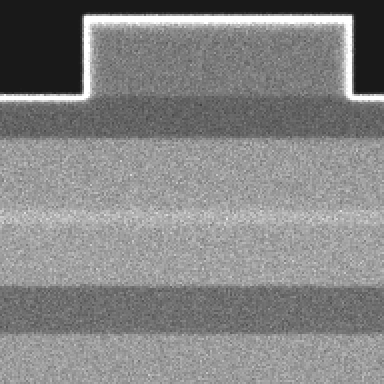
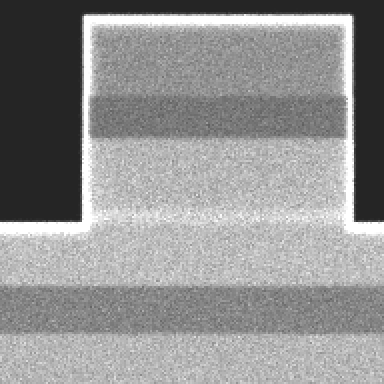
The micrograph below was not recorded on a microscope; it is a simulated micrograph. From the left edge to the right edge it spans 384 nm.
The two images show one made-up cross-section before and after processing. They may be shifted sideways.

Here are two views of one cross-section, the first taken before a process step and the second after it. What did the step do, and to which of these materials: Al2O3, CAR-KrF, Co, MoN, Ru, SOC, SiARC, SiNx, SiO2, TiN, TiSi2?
It removed Co and Ru and SiNx.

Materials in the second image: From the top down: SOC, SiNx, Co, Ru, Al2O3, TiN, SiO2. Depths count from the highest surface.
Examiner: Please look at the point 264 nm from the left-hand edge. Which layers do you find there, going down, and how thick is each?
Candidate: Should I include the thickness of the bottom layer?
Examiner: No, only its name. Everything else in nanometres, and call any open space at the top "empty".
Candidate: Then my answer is SOC 80, SiNx 42, Co 72, Ru 14, Al2O3 62, TiN 48, SiO2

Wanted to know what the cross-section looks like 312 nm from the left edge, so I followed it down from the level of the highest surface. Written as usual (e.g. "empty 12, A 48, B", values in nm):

SOC 80, SiNx 42, Co 72, Ru 14, Al2O3 62, TiN 48, SiO2